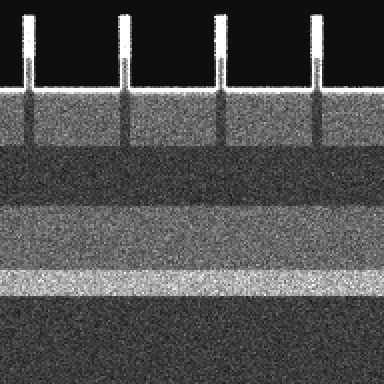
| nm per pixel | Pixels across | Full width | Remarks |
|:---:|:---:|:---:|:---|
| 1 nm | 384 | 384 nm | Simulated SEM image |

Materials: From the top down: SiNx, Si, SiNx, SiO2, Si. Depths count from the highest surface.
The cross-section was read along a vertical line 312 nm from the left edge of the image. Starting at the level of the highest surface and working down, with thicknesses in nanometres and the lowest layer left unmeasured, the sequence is Si 190, SiNx 64, SiO2 26, Si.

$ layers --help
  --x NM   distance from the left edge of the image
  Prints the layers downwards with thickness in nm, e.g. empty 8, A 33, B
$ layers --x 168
empty 72, SiNx 58, Si 60, SiNx 64, SiO2 26, Si